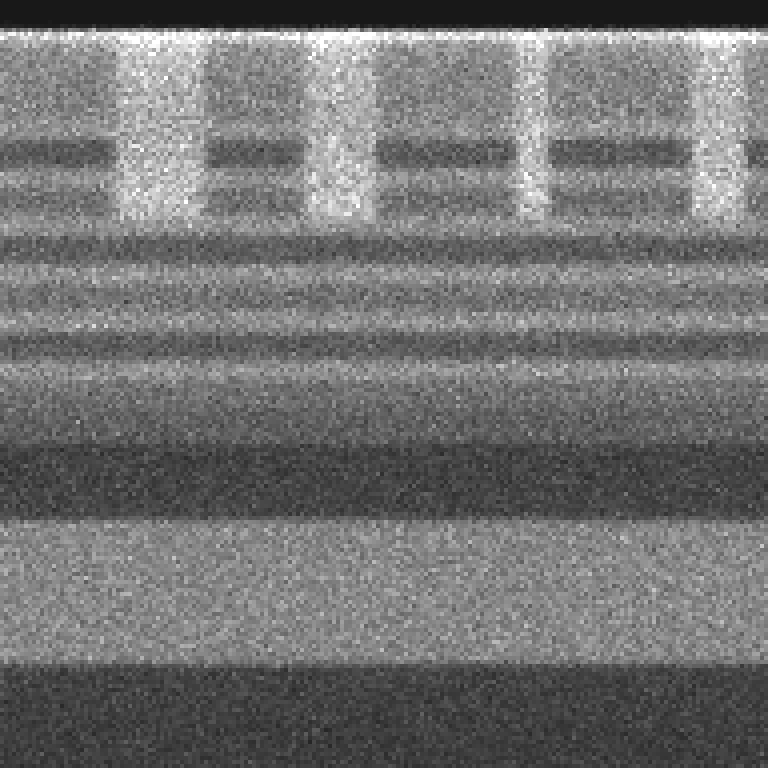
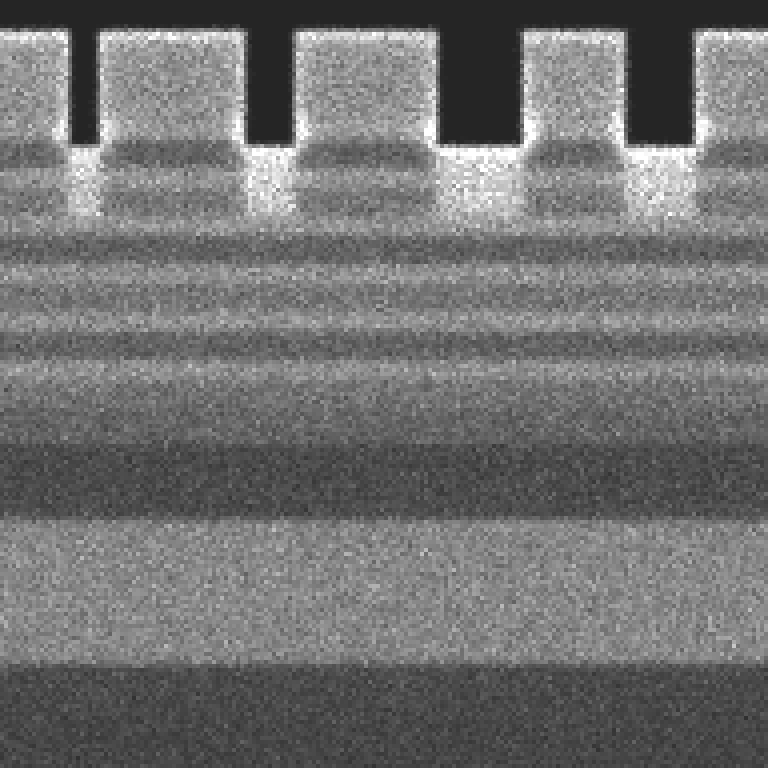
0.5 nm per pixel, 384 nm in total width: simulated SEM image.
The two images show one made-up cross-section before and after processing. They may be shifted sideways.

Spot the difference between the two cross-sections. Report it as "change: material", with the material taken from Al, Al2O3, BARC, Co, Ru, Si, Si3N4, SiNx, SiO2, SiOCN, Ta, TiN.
removed: Co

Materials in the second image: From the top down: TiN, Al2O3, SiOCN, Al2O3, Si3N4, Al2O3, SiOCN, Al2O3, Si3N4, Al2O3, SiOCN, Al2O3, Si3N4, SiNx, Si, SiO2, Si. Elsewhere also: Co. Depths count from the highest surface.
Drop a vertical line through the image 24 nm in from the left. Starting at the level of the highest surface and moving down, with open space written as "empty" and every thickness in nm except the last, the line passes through TiN 44, Al2O3 10, SiOCN 14, Al2O3 10, Si3N4 14, Al2O3 10, SiOCN 14, Al2O3 10, Si3N4 14, Al2O3 10, SiOCN 14, Al2O3 10, Si3N4 14, SiNx 18, Si 38, SiO2 72, Si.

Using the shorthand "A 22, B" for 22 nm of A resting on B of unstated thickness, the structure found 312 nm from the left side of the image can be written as empty 58, Co 34, Al2O3 10, SiOCN 14, Al2O3 10, Si3N4 14, Al2O3 10, SiOCN 14, Al2O3 10, Si3N4 14, SiNx 18, Si 38, SiO2 72, Si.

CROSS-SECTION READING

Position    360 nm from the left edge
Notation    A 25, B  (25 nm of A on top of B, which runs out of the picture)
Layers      TiN 44, Al2O3 10, SiOCN 14, Al2O3 10, Si3N4 14, Al2O3 10, SiOCN 14, Al2O3 10, Si3N4 14, Al2O3 10, SiOCN 14, Al2O3 10, Si3N4 14, SiNx 18, Si 38, SiO2 72, Si